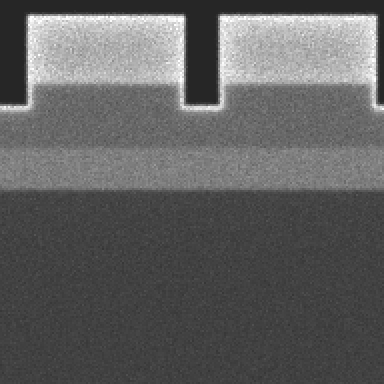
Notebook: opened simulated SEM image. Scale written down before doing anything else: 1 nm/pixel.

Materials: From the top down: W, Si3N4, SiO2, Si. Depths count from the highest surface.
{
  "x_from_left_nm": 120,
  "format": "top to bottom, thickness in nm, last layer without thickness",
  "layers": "W 68, Si3N4 64, SiO2 42, Si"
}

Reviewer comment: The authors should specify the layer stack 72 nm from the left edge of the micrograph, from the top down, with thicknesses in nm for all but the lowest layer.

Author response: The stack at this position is W 68, Si3N4 64, SiO2 42, Si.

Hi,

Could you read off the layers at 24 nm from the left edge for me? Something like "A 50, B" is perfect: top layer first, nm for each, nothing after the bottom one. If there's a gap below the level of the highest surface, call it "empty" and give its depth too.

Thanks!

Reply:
empty 90, Si3N4 42, SiO2 42, Si